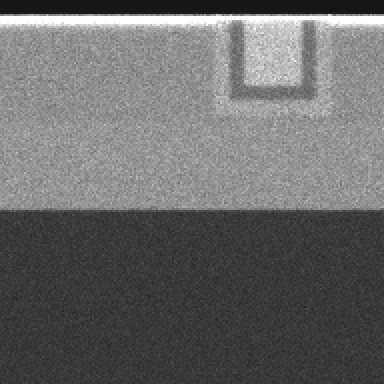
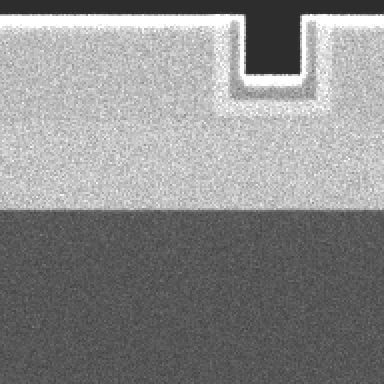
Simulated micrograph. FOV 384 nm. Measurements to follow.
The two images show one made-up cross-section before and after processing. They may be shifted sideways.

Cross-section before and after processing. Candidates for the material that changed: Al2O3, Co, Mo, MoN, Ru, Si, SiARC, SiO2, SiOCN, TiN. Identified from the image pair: Ru (removed).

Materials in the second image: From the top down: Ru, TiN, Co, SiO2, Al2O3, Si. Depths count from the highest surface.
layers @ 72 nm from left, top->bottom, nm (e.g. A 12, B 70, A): SiO2 106, Al2O3 88, Si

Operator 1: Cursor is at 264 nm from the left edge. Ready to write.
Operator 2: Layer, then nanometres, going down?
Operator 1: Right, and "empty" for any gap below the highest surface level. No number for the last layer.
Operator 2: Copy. empty 60, Ru 10, TiN 14, Co 16, SiO2 6, Al2O3 88, Si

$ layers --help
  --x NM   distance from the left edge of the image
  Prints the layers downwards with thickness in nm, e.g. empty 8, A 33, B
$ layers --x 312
TiN 84, Co 16, SiO2 6, Al2O3 88, Si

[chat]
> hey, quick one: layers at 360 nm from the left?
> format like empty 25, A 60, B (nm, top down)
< SiO2 106, Al2O3 88, Si